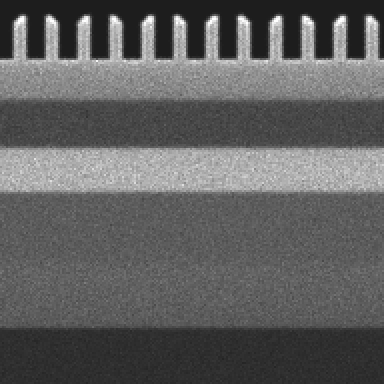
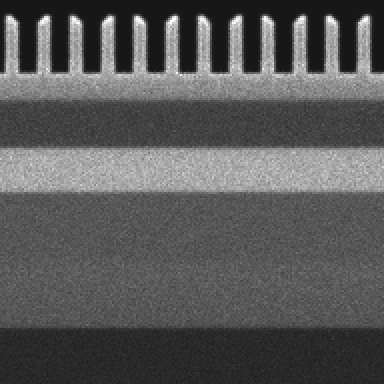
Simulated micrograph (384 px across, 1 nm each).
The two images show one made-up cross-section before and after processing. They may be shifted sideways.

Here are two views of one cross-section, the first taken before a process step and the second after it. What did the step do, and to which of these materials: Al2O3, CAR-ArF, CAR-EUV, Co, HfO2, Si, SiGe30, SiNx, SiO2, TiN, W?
It removed W.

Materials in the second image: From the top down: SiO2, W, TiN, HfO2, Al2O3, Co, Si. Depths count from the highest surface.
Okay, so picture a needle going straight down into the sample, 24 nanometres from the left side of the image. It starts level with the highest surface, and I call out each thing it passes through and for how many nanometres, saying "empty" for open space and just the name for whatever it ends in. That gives empty 58, W 26, TiN 48, HfO2 44, Al2O3 70, Co 66, Si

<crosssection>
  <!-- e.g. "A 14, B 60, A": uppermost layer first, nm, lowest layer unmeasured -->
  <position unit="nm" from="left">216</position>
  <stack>empty 58, W 26, TiN 48, HfO2 44, Al2O3 70, Co 66, Si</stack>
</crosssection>